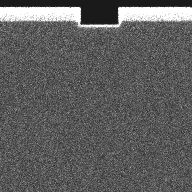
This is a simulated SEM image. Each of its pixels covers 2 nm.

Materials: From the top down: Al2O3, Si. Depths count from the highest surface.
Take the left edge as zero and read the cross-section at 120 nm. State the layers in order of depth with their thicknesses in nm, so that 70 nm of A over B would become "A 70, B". Al2O3 26, Si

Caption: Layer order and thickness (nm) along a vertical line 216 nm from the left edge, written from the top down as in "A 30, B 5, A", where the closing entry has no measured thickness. empty 34, Si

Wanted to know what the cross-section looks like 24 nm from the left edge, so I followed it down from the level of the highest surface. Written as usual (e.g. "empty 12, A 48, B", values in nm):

Al2O3 26, Si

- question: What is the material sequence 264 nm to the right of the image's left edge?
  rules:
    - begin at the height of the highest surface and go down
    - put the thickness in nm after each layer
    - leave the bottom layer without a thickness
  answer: Al2O3 26, Si